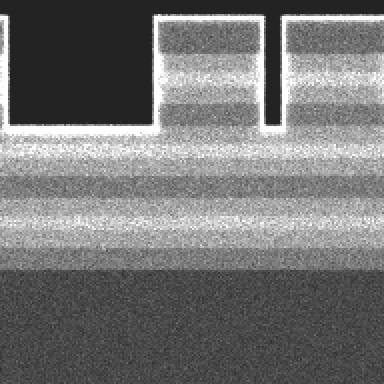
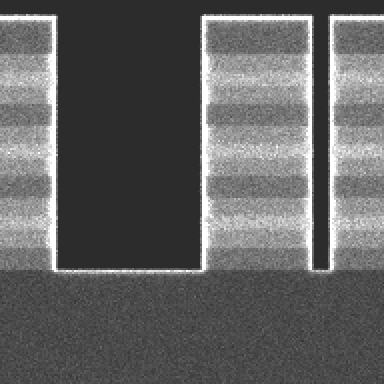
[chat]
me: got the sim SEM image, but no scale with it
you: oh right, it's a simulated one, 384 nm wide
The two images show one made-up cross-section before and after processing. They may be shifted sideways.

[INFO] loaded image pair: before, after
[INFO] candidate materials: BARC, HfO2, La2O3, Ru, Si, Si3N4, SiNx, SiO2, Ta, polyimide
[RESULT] removed Ru and Si3N4 and SiO2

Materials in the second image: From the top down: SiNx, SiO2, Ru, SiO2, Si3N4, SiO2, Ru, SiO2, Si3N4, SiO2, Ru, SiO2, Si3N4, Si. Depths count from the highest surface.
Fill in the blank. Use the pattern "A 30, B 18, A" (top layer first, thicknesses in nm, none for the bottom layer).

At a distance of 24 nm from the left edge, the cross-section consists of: SiNx 38, SiO2 18, Ru 14, SiO2 18, Si3N4 22, SiO2 18, Ru 14, SiO2 18, Si3N4 22, SiO2 18, Ru 14, SiO2 18, Si3N4 22, Si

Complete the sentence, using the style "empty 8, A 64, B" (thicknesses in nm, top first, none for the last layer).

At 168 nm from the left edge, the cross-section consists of empty 254, Si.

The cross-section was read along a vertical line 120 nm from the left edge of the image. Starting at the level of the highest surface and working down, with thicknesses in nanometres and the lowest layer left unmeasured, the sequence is empty 254, Si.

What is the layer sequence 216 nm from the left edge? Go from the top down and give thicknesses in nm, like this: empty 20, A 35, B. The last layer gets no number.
SiNx 38, SiO2 18, Ru 14, SiO2 18, Si3N4 22, SiO2 18, Ru 14, SiO2 18, Si3N4 22, SiO2 18, Ru 14, SiO2 18, Si3N4 22, Si